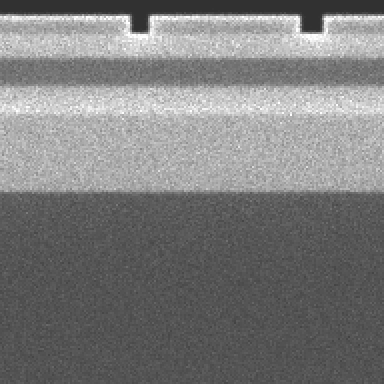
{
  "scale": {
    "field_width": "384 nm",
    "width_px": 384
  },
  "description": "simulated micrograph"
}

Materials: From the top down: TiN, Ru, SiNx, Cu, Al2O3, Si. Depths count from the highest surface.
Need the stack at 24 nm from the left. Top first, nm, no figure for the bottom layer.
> TiN 18, Ru 24, SiNx 28, Cu 28, Al2O3 78, Si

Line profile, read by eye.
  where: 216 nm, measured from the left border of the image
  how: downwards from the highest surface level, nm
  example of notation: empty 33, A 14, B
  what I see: TiN 18, Ru 24, SiNx 28, Cu 28, Al2O3 78, Si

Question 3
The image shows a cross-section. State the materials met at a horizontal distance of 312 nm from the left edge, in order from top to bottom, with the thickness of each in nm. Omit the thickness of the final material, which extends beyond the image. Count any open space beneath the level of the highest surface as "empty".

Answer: empty 18, Ru 24, SiNx 28, Cu 28, Al2O3 78, Si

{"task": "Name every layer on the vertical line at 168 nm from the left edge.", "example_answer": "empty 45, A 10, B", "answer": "TiN 18, Ru 24, SiNx 28, Cu 28, Al2O3 78, Si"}